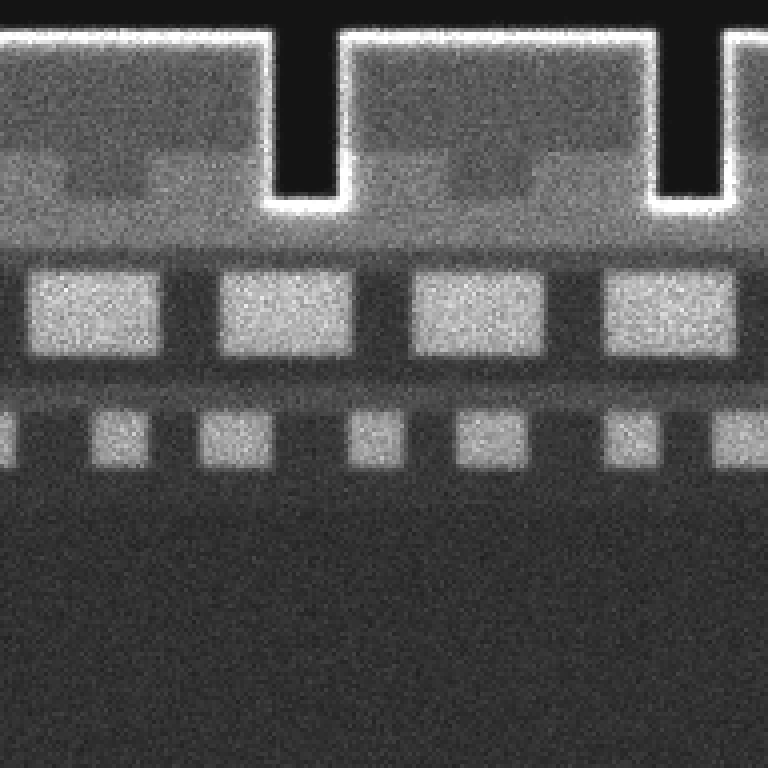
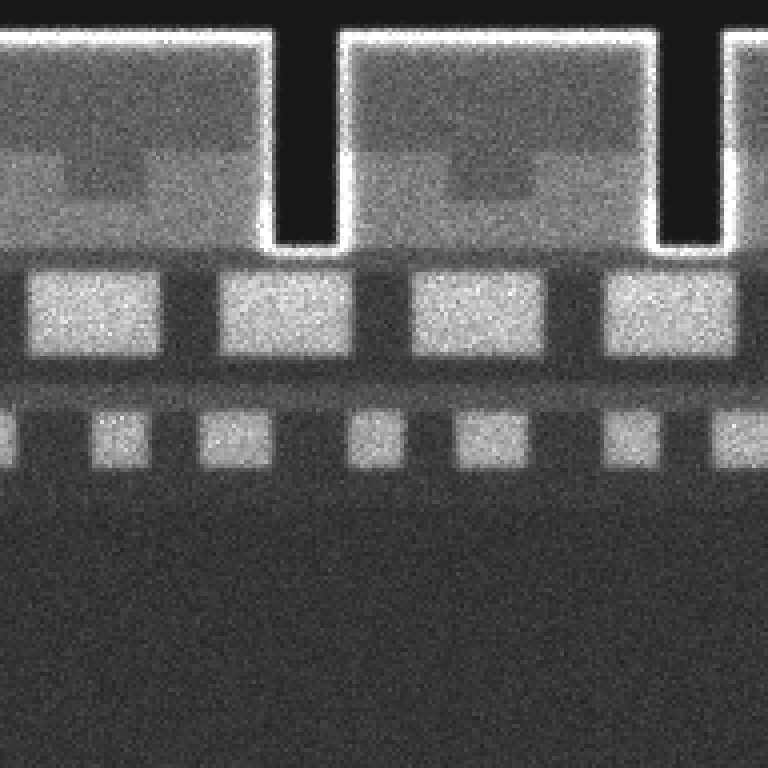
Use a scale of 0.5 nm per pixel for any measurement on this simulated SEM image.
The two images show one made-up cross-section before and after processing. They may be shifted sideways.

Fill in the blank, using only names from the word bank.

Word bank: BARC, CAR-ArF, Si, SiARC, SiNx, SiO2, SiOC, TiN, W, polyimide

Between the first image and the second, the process removed SiO2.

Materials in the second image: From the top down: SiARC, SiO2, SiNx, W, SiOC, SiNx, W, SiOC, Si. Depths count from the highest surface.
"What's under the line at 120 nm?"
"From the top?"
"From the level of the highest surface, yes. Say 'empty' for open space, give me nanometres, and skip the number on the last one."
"SiARC 60, SiO2 48, SiNx 12, W 42, SiOC 14, SiNx 14, W 28, SiOC 20, Si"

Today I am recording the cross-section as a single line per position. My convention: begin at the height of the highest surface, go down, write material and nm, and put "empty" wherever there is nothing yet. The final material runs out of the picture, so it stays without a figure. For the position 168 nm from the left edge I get empty 108, SiNx 12, W 42, SiOC 14, SiNx 14, SiOC 48, Si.